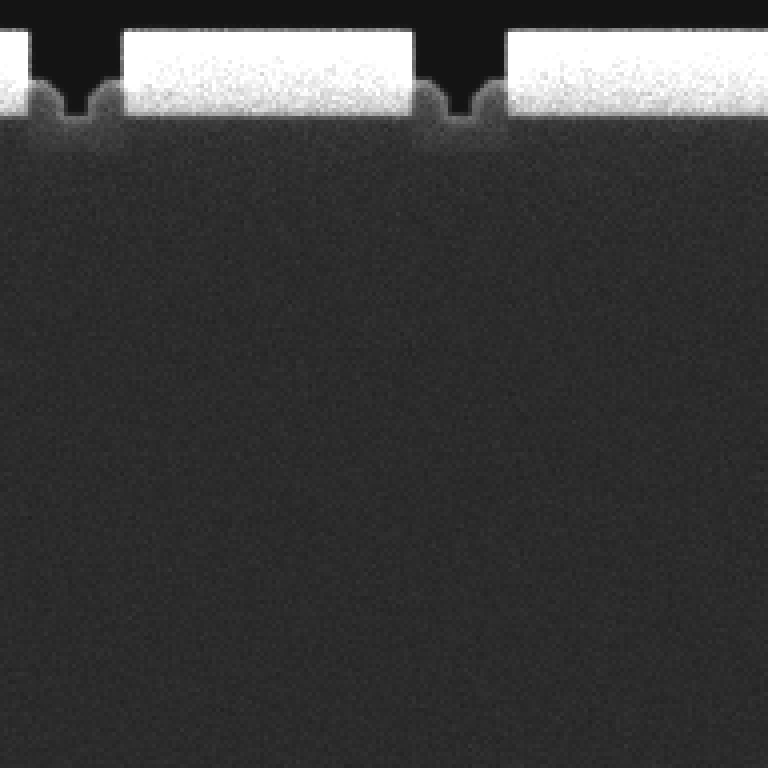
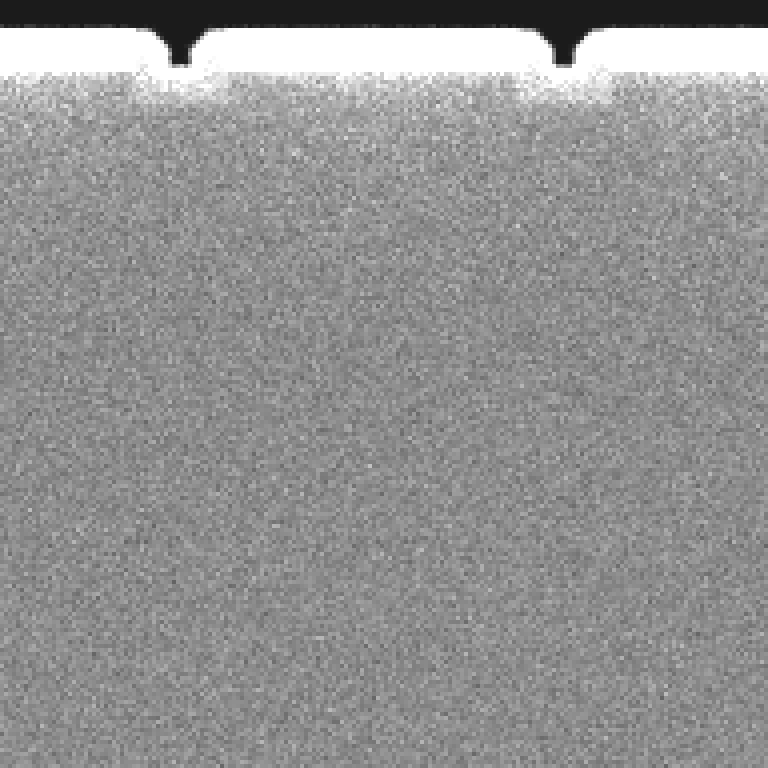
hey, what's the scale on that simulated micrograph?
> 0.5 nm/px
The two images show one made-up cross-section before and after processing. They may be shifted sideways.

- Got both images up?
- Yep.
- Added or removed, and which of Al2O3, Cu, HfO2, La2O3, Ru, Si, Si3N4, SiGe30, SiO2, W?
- removed, HfO2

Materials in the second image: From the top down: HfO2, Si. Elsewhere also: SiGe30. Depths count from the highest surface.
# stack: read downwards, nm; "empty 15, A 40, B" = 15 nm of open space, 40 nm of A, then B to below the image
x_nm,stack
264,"SiGe30 36, Si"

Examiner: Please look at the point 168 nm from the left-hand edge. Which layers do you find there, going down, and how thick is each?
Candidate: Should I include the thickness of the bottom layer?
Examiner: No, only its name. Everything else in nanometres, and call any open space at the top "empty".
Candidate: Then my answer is HfO2 18, Si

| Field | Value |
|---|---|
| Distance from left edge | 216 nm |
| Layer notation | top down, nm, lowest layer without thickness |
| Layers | HfO2 18, Si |